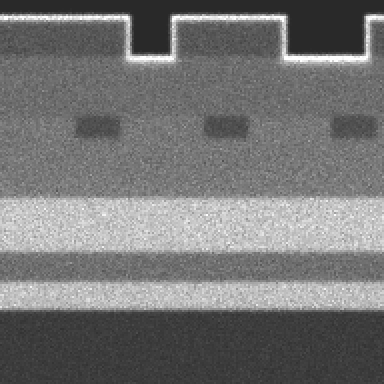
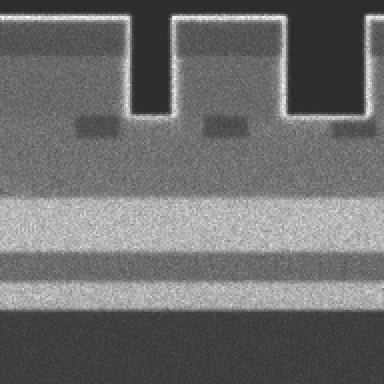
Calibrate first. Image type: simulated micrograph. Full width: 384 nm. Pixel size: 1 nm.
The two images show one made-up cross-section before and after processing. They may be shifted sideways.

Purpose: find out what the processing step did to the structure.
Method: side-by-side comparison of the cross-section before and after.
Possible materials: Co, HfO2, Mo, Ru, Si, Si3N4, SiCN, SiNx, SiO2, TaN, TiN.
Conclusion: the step removed SiO2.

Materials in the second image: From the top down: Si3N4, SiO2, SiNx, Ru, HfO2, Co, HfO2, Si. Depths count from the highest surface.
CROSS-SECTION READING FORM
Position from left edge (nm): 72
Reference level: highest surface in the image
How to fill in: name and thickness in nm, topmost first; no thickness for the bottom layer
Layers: Si3N4 40, SiO2 60, Ru 82, HfO2 54, Co 30, HfO2 28, Si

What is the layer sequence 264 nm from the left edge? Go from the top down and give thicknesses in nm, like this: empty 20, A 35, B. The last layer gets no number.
Si3N4 40, SiO2 60, Ru 82, HfO2 54, Co 30, HfO2 28, Si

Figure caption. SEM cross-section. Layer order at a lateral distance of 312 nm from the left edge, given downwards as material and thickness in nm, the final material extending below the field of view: empty 100, Ru 82, HfO2 54, Co 30, HfO2 28, Si